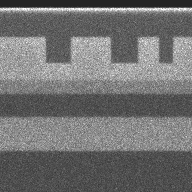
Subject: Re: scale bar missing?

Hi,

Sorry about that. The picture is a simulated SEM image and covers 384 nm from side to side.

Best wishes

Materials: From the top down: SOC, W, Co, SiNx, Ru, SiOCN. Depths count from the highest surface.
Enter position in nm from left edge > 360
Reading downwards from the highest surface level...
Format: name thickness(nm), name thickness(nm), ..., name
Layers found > SOC 58, W 86, Co 28, SiNx 46, Ru 68, SiOCN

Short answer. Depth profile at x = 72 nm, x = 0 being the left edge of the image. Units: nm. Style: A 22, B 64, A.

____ SOC 58, W 86, Co 28, SiNx 46, Ru 68, SiOCN